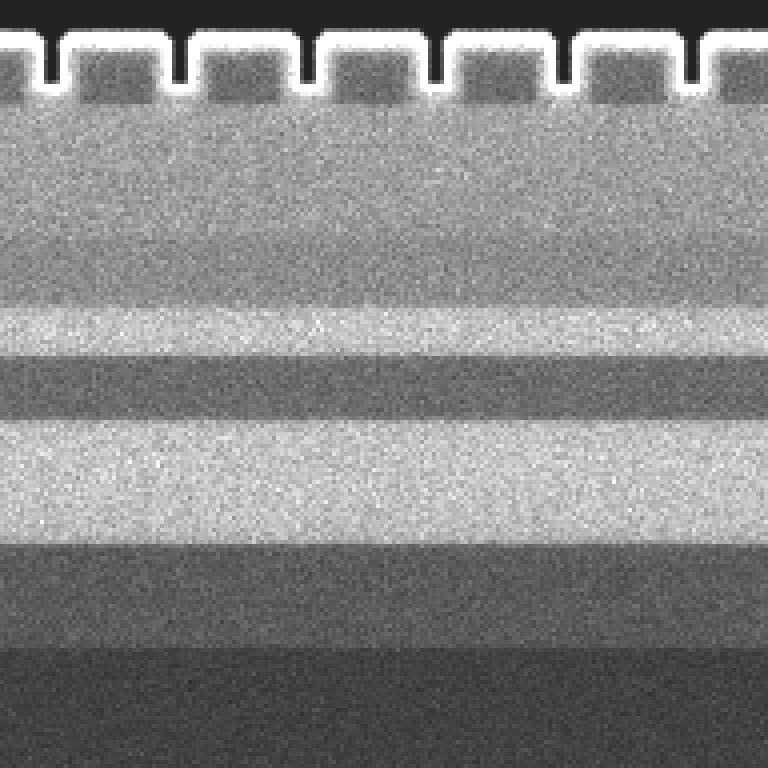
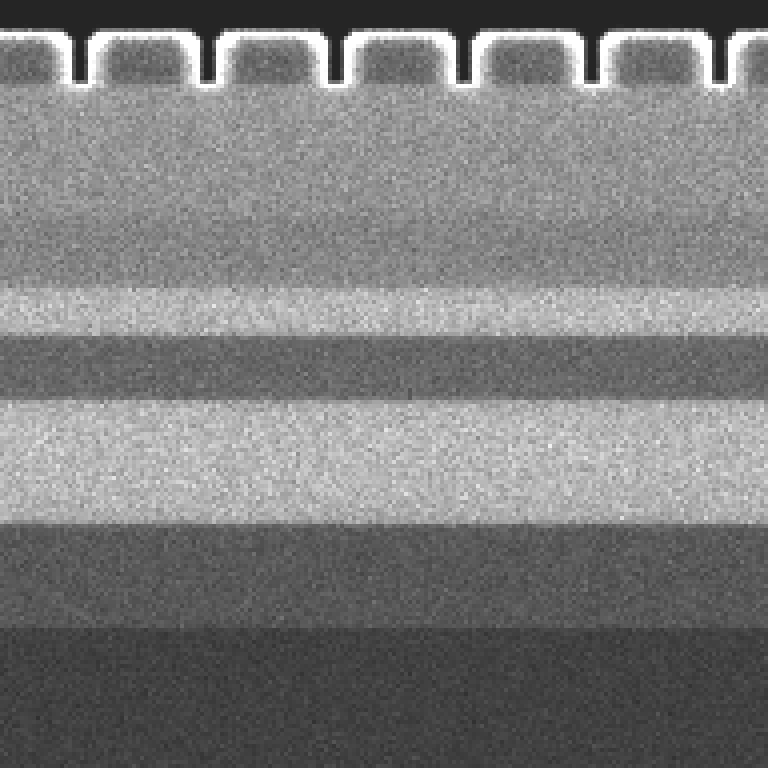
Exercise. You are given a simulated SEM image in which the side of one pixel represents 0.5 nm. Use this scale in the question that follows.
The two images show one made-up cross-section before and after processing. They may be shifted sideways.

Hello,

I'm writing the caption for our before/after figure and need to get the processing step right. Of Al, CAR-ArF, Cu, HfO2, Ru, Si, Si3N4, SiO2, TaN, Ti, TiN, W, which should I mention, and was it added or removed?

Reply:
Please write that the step removed SiO2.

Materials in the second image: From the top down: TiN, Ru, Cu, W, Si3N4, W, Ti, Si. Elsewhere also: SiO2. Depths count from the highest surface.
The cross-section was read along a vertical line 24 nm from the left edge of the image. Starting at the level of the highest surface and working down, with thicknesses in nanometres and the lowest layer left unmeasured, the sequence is TiN 26, Ru 66, Cu 36, W 24, Si3N4 32, W 62, Ti 52, Si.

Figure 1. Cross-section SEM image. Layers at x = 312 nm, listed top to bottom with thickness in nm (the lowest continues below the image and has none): TiN 26, Ru 66, Cu 36, W 24, Si3N4 32, W 62, Ti 52, Si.